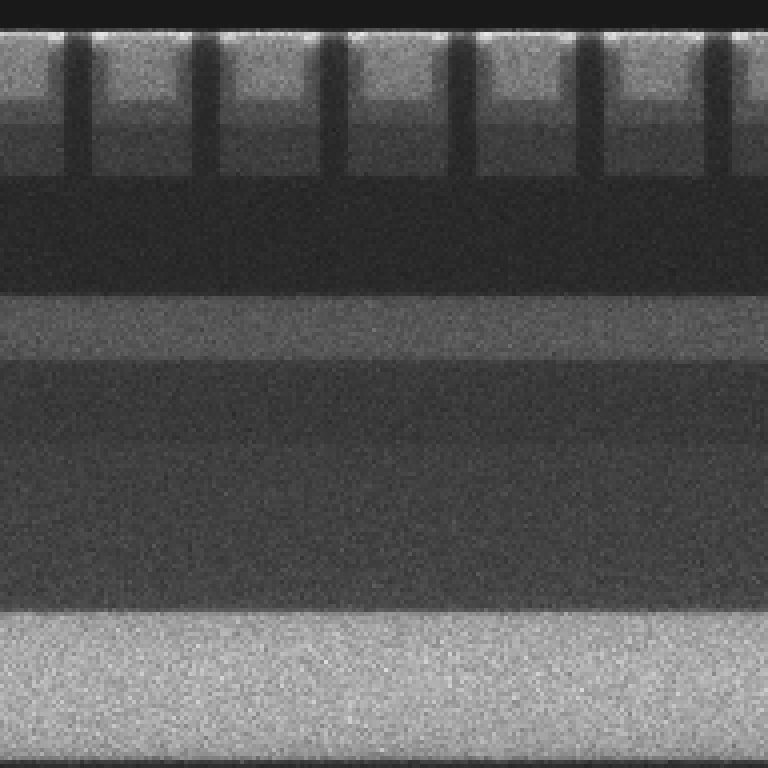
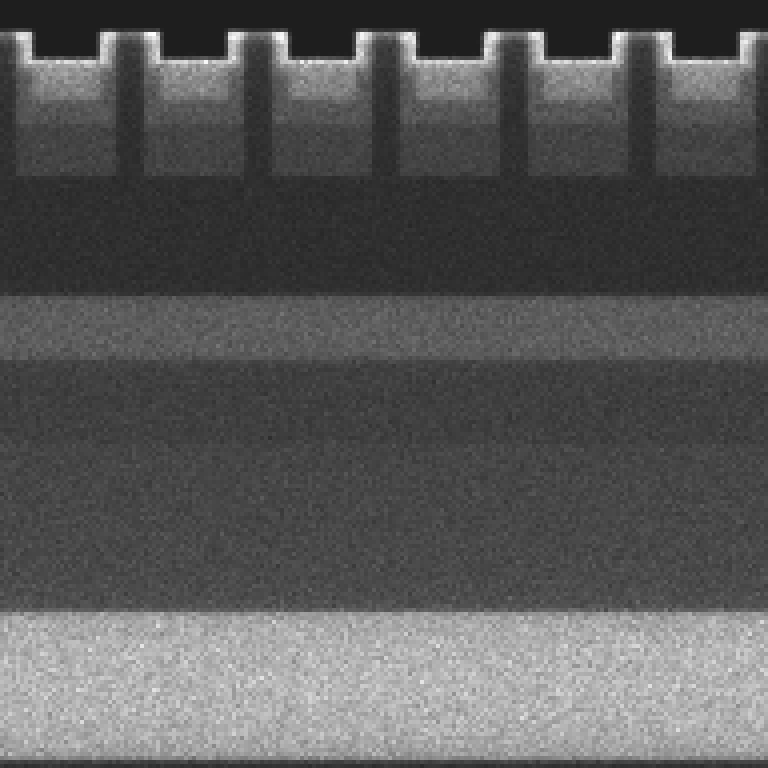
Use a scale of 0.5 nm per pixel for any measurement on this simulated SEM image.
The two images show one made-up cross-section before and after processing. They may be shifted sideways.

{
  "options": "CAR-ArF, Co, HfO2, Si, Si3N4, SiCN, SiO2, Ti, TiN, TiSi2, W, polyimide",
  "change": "removed",
  "material": "W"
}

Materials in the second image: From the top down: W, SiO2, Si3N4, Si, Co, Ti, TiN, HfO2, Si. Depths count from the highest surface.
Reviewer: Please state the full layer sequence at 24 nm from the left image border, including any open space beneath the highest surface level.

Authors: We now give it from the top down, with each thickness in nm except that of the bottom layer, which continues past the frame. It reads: empty 14, W 20, SiO2 12, Si3N4 26, Si 60, Co 32, Ti 42, TiN 84, HfO2 74, Si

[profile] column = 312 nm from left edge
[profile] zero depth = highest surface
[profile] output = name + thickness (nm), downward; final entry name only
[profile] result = SiO2 46, Si3N4 26, Si 60, Co 32, Ti 42, TiN 84, HfO2 74, Si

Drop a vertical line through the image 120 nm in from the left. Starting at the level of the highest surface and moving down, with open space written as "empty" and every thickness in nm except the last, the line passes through SiO2 46, Si3N4 26, Si 60, Co 32, Ti 42, TiN 84, HfO2 74, Si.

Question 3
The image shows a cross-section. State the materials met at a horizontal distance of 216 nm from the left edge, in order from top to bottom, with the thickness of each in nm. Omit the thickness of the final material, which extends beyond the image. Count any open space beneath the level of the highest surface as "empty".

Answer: empty 14, W 20, SiO2 12, Si3N4 26, Si 60, Co 32, Ti 42, TiN 84, HfO2 74, Si